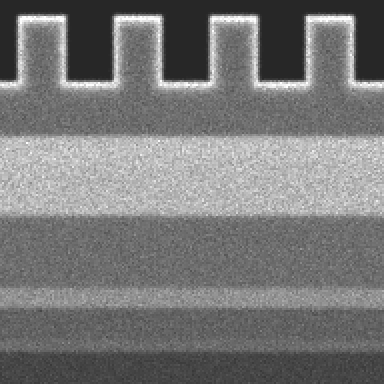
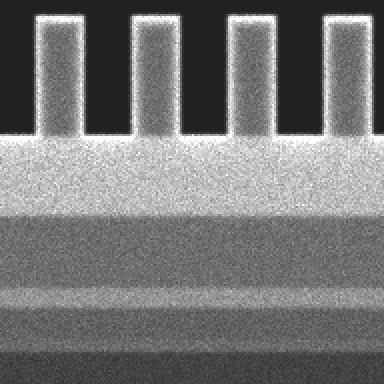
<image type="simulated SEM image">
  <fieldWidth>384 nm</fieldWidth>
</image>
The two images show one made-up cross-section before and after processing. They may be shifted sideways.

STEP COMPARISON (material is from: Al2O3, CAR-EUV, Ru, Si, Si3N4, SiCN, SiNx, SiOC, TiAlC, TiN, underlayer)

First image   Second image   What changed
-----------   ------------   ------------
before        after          underlayer, removed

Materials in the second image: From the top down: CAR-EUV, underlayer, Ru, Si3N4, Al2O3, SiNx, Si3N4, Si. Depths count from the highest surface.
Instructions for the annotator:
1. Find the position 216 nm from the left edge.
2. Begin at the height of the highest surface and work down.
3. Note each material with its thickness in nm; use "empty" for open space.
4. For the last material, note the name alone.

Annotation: empty 120, Ru 80, Si3N4 72, Al2O3 20, SiNx 32, Si3N4 12, Si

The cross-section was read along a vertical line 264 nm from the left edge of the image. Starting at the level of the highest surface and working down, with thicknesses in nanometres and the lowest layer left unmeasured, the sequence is CAR-EUV 66, underlayer 54, Ru 80, Si3N4 72, Al2O3 20, SiNx 32, Si3N4 12, Si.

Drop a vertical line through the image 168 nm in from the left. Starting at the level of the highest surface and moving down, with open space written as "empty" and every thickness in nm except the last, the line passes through CAR-EUV 66, underlayer 54, Ru 80, Si3N4 72, Al2O3 20, SiNx 32, Si3N4 12, Si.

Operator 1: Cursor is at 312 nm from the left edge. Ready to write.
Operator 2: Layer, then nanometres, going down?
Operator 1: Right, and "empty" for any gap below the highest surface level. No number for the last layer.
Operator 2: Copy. empty 120, Ru 80, Si3N4 72, Al2O3 20, SiNx 32, Si3N4 12, Si